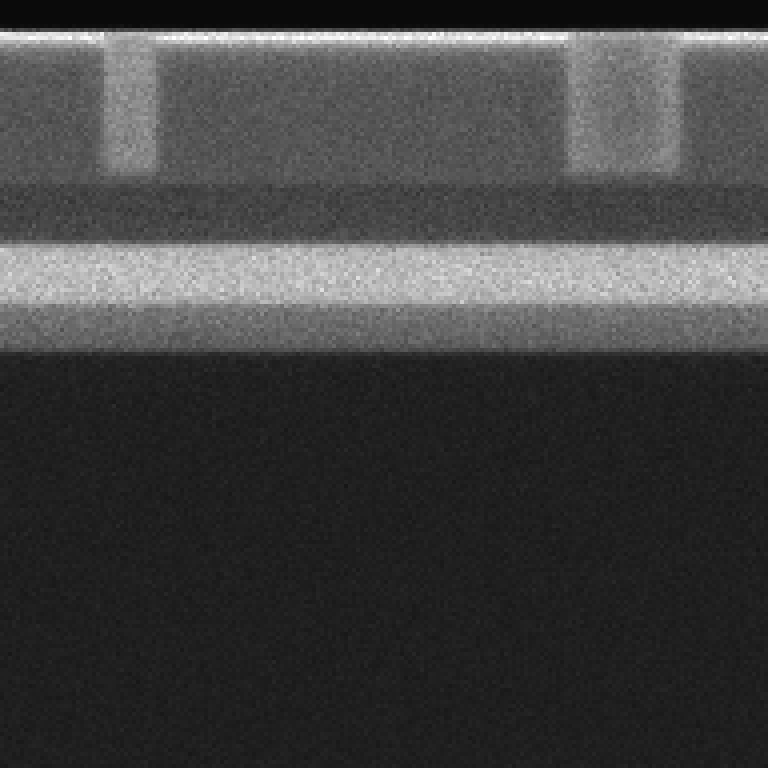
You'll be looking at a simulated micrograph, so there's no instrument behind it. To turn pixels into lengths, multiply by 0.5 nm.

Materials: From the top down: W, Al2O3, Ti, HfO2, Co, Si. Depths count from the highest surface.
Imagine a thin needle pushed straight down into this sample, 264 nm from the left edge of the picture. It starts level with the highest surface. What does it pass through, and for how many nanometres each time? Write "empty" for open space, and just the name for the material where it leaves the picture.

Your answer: Al2O3 76, Ti 30, HfO2 30, Co 24, Si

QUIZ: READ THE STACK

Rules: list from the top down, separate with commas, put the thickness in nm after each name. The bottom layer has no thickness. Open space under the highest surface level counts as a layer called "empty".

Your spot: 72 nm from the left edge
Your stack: W 70, Al2O3 6, Ti 30, HfO2 30, Co 24, Si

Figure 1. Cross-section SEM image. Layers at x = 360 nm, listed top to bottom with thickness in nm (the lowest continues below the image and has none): Al2O3 76, Ti 30, HfO2 30, Co 24, Si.